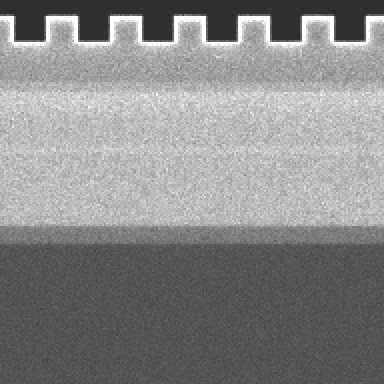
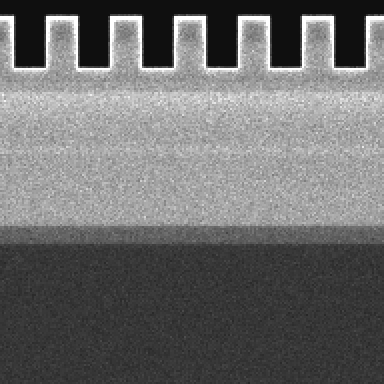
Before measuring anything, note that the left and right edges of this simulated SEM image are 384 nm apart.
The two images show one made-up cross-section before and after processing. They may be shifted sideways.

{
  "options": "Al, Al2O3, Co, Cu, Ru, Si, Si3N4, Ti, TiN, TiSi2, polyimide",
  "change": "removed",
  "material": "TiN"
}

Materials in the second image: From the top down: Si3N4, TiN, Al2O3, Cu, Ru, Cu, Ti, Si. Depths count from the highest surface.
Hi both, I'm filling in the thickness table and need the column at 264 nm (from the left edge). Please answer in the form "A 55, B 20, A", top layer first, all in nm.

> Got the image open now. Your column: Si3N4 26, TiN 40, Al2O3 10, Cu 54, Ru 8, Cu 72, Ti 18, Si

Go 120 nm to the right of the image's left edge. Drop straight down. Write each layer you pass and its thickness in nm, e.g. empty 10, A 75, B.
Si3N4 26, TiN 40, Al2O3 10, Cu 54, Ru 8, Cu 72, Ti 18, Si